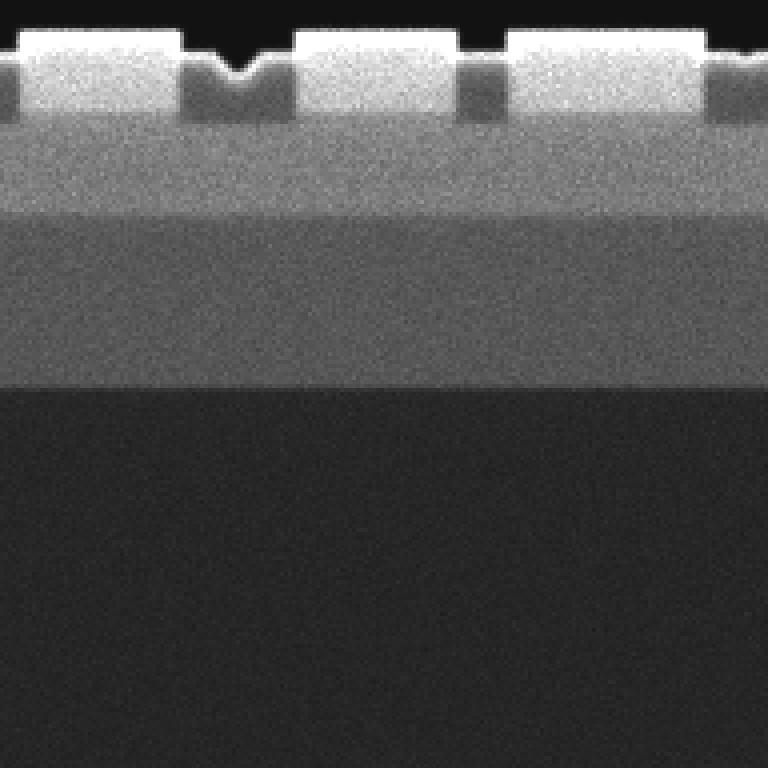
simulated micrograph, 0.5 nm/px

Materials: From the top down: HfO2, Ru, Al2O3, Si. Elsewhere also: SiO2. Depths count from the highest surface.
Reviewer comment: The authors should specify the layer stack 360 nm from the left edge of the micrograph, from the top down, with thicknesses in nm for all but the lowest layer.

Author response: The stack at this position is empty 10, SiO2 36, Ru 46, Al2O3 86, Si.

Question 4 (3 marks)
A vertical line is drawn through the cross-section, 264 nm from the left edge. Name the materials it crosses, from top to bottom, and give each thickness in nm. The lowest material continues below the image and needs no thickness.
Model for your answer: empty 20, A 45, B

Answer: HfO2 40, Ru 52, Al2O3 86, Si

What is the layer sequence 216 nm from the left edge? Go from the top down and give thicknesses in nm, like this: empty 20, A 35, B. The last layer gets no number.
HfO2 40, Ru 52, Al2O3 86, Si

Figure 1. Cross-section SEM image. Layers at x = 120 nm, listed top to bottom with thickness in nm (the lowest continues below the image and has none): empty 20, SiO2 26, Ru 46, Al2O3 86, Si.